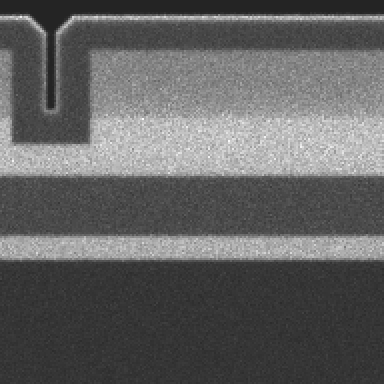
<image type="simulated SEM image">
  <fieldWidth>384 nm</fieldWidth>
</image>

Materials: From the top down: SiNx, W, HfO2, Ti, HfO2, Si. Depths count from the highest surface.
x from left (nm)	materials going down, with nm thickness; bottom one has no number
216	SiNx 34, W 68, HfO2 58, Ti 60, HfO2 24, Si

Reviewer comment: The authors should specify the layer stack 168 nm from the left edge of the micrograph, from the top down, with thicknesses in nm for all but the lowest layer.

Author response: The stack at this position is SiNx 34, W 68, HfO2 58, Ti 60, HfO2 24, Si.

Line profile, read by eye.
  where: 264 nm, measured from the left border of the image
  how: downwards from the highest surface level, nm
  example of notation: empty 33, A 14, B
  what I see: SiNx 34, W 68, HfO2 58, Ti 60, HfO2 24, Si